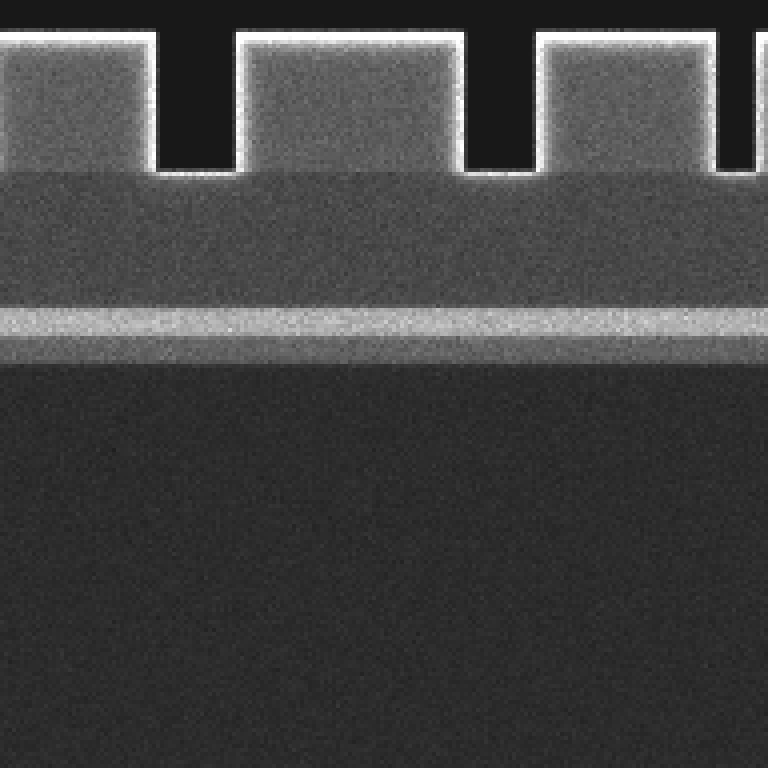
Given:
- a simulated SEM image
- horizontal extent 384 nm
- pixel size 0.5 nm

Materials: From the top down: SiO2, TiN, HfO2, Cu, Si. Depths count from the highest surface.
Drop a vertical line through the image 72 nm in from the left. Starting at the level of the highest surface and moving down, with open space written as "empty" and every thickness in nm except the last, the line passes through SiO2 70, TiN 68, HfO2 14, Cu 14, Si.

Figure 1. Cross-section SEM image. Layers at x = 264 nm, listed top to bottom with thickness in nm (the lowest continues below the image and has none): empty 70, TiN 68, HfO2 14, Cu 14, Si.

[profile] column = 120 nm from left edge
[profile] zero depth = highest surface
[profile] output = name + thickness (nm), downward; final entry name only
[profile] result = SiO2 70, TiN 68, HfO2 14, Cu 14, Si